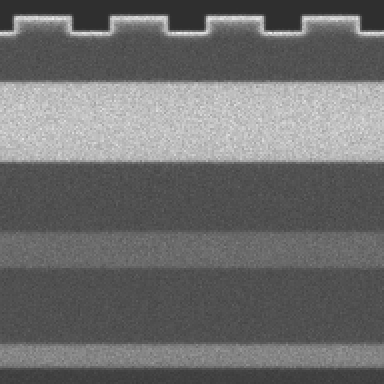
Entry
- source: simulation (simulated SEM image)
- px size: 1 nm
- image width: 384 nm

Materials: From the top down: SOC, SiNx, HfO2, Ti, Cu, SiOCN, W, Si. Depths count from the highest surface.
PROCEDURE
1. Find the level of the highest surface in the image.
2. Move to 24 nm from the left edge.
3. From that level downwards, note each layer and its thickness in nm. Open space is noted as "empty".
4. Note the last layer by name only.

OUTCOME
SOC 16, SiNx 50, HfO2 80, Ti 70, Cu 36, SiOCN 76, W 24, Si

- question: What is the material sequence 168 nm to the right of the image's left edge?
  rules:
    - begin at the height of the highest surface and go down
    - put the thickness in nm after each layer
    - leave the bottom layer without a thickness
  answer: empty 16, SiNx 50, HfO2 80, Ti 70, Cu 36, SiOCN 76, W 24, Si